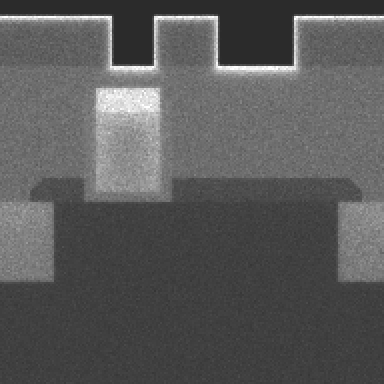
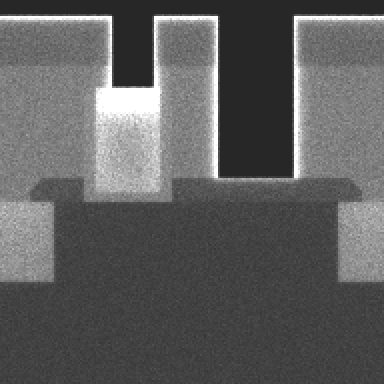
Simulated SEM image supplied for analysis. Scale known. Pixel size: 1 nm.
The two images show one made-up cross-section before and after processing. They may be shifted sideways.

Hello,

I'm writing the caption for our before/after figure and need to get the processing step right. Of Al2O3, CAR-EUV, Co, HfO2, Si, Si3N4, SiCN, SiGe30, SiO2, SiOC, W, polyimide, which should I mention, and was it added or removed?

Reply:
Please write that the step removed SiO2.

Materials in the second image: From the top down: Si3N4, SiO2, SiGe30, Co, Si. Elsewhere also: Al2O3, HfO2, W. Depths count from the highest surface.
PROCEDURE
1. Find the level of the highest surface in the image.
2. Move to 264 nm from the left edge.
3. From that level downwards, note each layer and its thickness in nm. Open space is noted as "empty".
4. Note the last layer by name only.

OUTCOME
empty 162, SiGe30 24, Si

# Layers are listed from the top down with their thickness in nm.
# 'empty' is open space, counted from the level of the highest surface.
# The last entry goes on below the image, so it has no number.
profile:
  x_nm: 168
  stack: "Si3N4 50, SiO2 26, Al2O3 110, Si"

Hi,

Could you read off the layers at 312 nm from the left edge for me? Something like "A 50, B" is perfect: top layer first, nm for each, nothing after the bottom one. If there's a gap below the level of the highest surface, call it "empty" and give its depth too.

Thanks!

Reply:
Si3N4 50, SiO2 112, SiGe30 24, Si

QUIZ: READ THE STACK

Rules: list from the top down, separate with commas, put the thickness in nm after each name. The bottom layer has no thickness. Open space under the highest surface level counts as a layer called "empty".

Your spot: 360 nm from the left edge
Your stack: Si3N4 50, SiO2 124, SiGe30 12, Co 80, Si